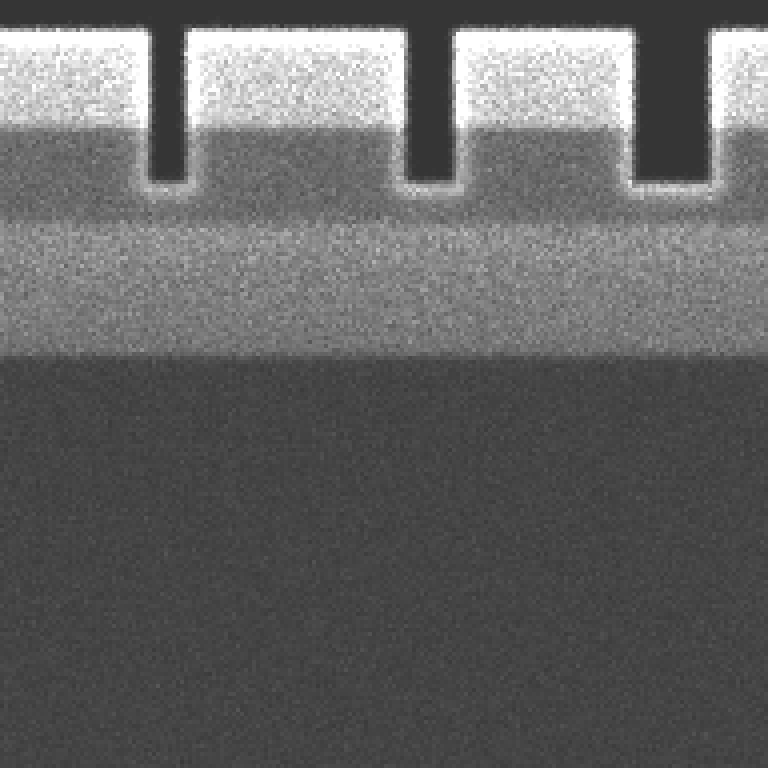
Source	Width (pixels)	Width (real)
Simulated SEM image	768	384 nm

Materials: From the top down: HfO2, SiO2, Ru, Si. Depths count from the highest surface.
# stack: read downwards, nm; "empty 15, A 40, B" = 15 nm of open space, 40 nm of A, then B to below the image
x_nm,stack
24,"HfO2 48, SiO2 48, Ru 66, Si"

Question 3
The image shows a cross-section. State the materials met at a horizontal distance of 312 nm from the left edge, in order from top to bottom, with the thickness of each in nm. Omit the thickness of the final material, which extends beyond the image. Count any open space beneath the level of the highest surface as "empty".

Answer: HfO2 48, SiO2 48, Ru 66, Si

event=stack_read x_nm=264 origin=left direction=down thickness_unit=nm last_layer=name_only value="HfO2 48, SiO2 48, Ru 66, Si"